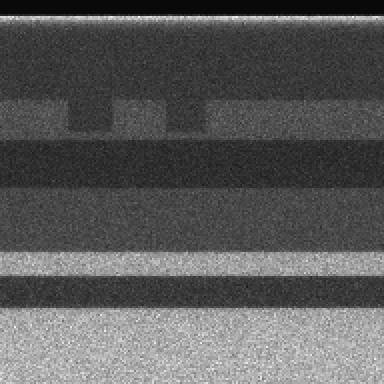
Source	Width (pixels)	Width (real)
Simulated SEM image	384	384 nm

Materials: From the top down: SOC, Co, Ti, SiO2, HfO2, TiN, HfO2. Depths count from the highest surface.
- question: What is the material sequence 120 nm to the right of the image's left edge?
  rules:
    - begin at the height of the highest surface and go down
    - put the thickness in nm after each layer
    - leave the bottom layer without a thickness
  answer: SOC 84, Co 40, Ti 48, SiO2 64, HfO2 24, TiN 32, HfO2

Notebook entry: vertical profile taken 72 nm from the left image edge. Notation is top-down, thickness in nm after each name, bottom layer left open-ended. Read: SOC 116, Co 8, Ti 48, SiO2 64, HfO2 24, TiN 32, HfO2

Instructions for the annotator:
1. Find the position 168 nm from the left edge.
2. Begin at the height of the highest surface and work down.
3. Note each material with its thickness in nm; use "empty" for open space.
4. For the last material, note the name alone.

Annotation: SOC 116, Co 8, Ti 48, SiO2 64, HfO2 24, TiN 32, HfO2